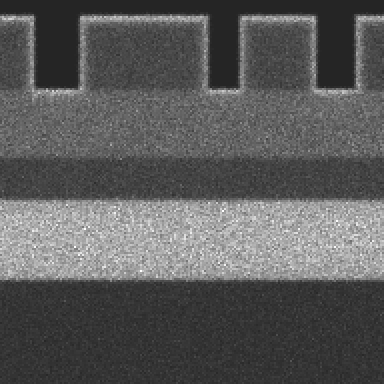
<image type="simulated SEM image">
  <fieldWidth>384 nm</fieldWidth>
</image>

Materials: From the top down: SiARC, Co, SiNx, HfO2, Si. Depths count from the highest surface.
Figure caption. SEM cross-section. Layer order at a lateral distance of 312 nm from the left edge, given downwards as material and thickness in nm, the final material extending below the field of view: SiARC 74, Co 68, SiNx 42, HfO2 80, Si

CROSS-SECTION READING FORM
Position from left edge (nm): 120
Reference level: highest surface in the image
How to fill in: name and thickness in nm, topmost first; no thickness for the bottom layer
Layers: SiARC 74, Co 68, SiNx 42, HfO2 80, Si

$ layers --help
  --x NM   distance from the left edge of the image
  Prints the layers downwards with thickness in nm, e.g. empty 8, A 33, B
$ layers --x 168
SiARC 74, Co 68, SiNx 42, HfO2 80, Si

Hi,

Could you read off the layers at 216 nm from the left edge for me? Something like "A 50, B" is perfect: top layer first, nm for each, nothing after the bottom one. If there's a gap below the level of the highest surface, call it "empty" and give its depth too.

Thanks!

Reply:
empty 74, Co 68, SiNx 42, HfO2 80, Si